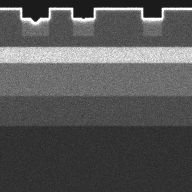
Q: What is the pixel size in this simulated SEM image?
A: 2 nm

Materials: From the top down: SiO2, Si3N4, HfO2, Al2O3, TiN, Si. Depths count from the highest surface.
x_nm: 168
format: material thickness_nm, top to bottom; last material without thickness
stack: empty 22, SiO2 34, Si3N4 22, HfO2 32, Al2O3 66, TiN 60, Si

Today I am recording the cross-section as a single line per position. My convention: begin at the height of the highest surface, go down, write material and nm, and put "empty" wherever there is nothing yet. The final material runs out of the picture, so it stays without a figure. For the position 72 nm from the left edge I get empty 28, SiO2 28, Si3N4 22, HfO2 32, Al2O3 66, TiN 60, Si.